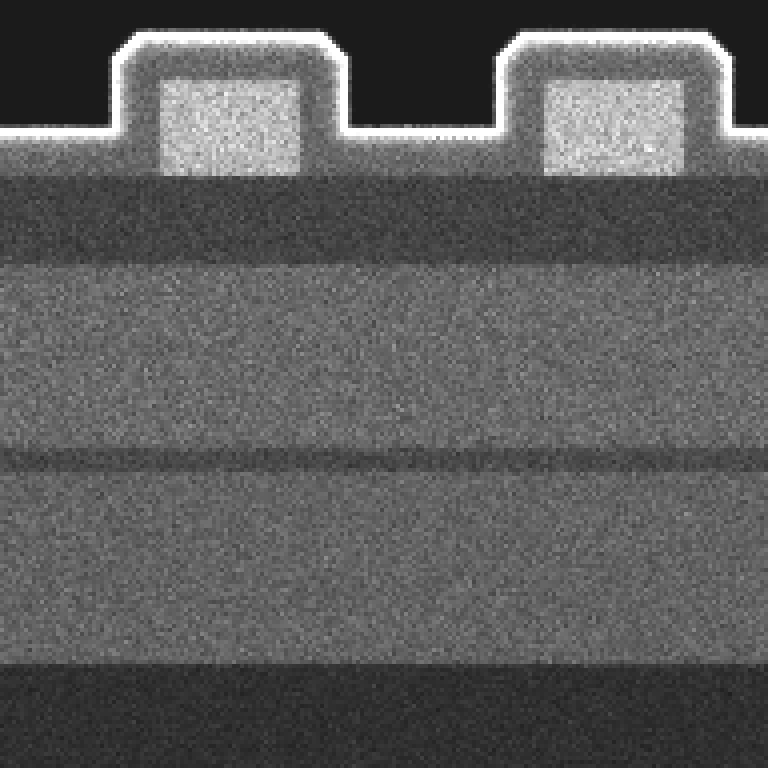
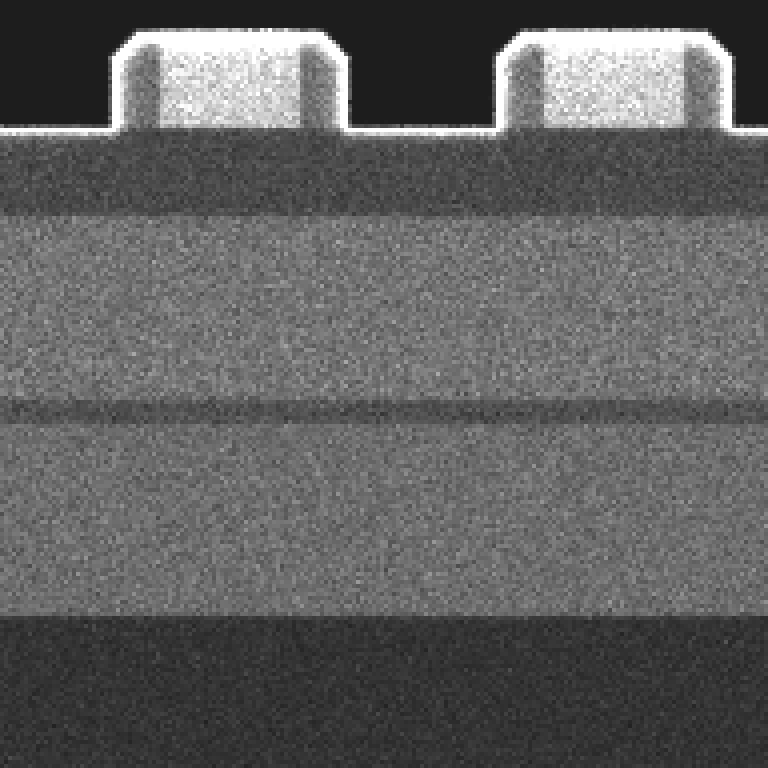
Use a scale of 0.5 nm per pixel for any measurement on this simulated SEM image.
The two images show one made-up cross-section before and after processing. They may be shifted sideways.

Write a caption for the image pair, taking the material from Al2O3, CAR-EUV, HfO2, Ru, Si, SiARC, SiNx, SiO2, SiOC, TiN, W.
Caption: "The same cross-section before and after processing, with Al2O3 removed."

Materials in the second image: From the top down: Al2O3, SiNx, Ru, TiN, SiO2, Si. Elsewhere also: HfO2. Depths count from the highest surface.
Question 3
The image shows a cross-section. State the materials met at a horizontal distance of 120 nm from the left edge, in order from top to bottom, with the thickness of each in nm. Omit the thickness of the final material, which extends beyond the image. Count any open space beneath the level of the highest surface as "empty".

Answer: HfO2 48, SiNx 44, Ru 92, TiN 12, SiO2 96, Si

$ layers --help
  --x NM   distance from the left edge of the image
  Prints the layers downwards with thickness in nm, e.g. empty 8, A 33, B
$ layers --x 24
empty 48, SiNx 44, Ru 92, TiN 12, SiO2 96, Si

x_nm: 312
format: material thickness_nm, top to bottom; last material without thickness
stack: HfO2 48, SiNx 44, Ru 92, TiN 12, SiO2 96, Si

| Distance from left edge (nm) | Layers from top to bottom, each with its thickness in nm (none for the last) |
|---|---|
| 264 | Al2O3 48, SiNx 44, Ru 92, TiN 12, SiO2 96, Si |